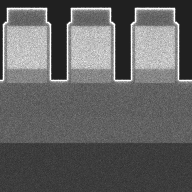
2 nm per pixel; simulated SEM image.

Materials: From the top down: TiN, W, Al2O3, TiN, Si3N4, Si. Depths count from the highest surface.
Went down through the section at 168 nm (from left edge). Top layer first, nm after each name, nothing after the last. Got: TiN 36, W 86, Al2O3 28, TiN 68, Si3N4 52, Si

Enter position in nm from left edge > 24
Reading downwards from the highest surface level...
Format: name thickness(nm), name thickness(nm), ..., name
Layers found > TiN 36, W 86, Al2O3 28, TiN 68, Si3N4 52, Si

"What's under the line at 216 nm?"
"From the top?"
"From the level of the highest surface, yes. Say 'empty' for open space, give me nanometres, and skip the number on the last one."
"TiN 36, W 86, Al2O3 28, TiN 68, Si3N4 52, Si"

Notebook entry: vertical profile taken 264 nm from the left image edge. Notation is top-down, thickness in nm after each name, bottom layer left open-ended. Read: empty 30, TiN 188, Si3N4 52, Si